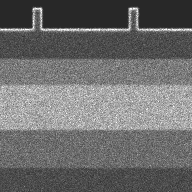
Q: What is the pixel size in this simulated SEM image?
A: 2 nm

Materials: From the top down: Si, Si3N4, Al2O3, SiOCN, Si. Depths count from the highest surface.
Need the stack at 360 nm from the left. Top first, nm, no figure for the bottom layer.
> empty 42, Si 60, Si3N4 52, Al2O3 90, SiOCN 76, Si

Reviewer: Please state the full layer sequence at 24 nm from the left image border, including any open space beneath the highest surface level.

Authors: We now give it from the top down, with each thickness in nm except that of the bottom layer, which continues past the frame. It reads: empty 42, Si 60, Si3N4 52, Al2O3 90, SiOCN 76, Si